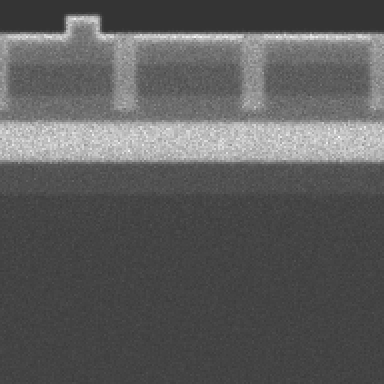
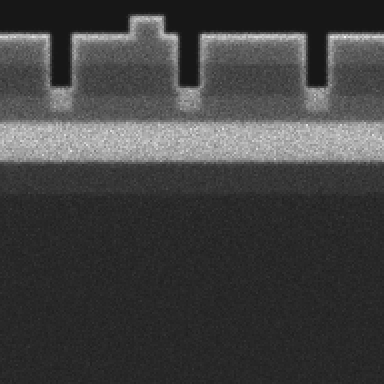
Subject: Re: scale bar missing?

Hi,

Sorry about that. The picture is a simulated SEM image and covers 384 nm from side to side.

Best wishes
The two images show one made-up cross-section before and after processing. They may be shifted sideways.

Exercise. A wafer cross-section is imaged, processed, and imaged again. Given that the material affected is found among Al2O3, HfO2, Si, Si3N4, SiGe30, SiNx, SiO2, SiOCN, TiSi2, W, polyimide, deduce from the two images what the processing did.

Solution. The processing removed W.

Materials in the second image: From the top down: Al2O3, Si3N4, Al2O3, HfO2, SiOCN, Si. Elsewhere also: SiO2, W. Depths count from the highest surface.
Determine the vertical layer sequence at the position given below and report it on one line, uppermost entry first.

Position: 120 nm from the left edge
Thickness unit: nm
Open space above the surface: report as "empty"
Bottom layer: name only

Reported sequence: empty 18, Al2O3 30, Si3N4 32, Al2O3 26, HfO2 40, SiOCN 32, Si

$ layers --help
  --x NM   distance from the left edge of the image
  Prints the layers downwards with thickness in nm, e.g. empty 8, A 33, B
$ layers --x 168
empty 18, Al2O3 30, Si3N4 32, Al2O3 26, HfO2 40, SiOCN 32, Si